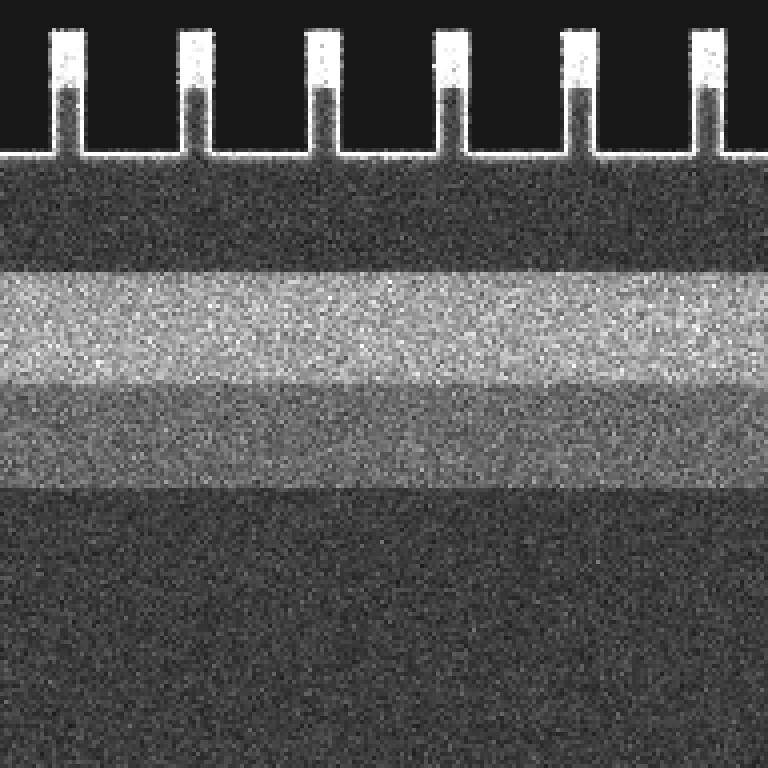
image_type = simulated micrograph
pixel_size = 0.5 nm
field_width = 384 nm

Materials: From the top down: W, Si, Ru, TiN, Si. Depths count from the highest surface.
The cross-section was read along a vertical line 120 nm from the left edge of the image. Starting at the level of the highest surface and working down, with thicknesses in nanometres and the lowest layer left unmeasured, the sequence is empty 60, Si 60, Ru 56, TiN 52, Si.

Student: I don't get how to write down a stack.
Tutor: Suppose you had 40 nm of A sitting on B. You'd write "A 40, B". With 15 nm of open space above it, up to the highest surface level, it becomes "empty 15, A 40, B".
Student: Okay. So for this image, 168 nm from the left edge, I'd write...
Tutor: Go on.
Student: W 28, Si 92, Ru 56, TiN 52, Si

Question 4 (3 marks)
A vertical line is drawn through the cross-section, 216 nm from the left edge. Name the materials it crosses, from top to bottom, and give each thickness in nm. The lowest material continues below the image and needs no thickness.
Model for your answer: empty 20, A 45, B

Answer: empty 60, Si 60, Ru 56, TiN 52, Si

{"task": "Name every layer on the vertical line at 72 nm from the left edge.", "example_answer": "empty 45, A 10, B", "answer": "empty 60, Si 60, Ru 56, TiN 52, Si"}